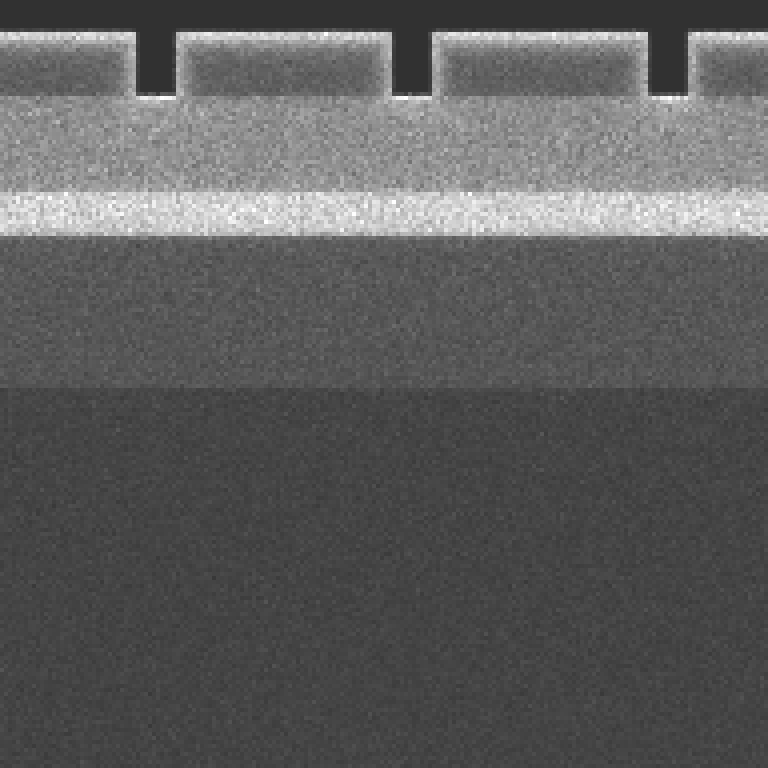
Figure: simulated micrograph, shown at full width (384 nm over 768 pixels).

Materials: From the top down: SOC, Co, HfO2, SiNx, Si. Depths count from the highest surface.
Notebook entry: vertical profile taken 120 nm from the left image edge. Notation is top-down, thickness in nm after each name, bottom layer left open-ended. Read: SOC 32, Co 48, HfO2 22, SiNx 76, Si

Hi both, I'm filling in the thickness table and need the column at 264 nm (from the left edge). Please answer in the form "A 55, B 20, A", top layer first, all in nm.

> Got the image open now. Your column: SOC 32, Co 48, HfO2 22, SiNx 76, Si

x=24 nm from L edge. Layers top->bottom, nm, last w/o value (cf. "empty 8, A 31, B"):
SOC 32, Co 48, HfO2 22, SiNx 76, Si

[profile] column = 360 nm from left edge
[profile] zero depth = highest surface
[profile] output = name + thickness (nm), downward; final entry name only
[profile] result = SOC 32, Co 48, HfO2 22, SiNx 76, Si